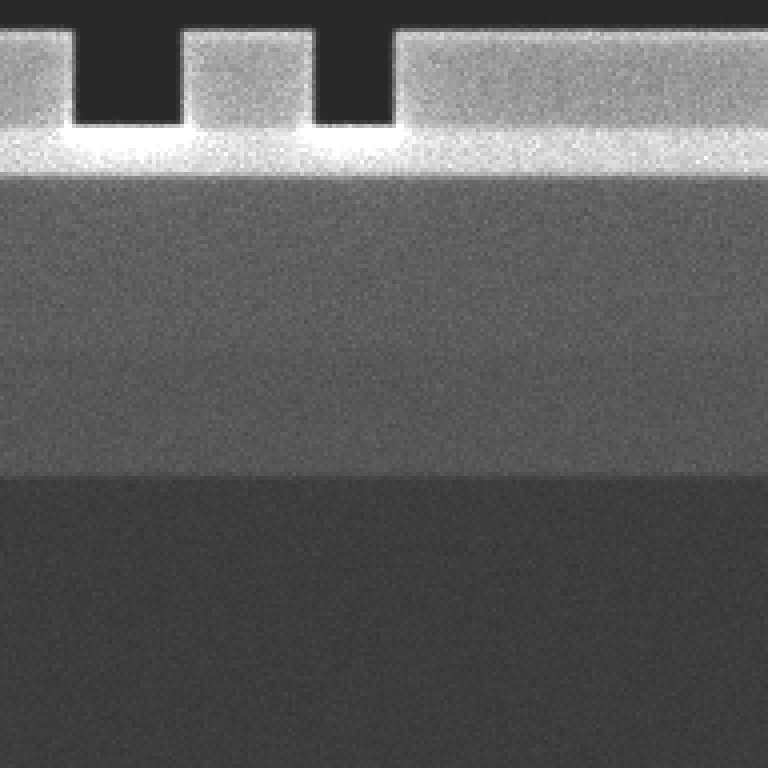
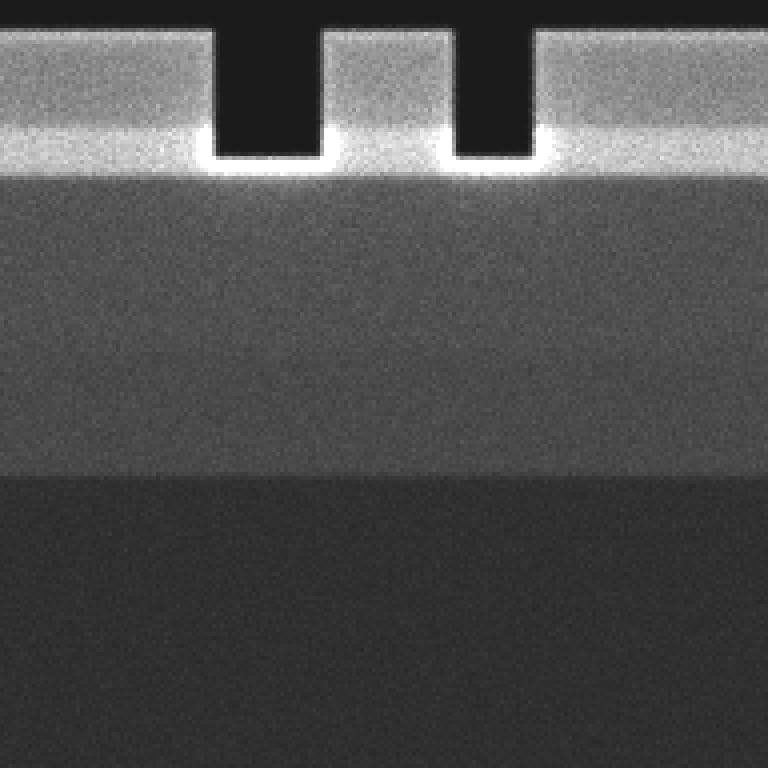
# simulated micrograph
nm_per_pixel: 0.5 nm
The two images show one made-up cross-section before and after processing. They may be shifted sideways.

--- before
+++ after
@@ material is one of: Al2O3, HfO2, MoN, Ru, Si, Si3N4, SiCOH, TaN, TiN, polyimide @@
HfO2 removed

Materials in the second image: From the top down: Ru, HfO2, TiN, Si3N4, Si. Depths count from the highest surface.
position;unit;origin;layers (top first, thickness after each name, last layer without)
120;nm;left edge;empty 64, HfO2 8, TiN 88, Si3N4 62, Si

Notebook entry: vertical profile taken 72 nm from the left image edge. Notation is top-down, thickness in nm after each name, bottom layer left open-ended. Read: Ru 48, HfO2 24, TiN 88, Si3N4 62, Si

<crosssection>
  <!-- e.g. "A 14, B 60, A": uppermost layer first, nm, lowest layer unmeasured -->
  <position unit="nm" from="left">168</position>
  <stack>Ru 48, HfO2 24, TiN 88, Si3N4 62, Si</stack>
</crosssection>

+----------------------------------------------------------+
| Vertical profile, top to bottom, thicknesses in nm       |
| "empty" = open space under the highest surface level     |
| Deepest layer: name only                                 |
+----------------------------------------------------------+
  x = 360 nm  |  Ru 48, HfO2 24, TiN 88, Si3N4 62, Si